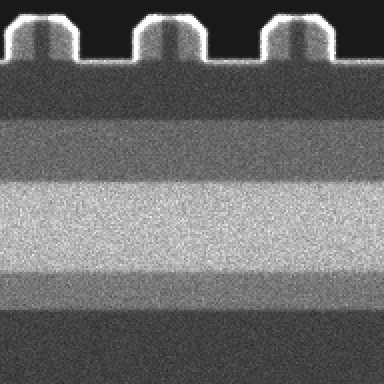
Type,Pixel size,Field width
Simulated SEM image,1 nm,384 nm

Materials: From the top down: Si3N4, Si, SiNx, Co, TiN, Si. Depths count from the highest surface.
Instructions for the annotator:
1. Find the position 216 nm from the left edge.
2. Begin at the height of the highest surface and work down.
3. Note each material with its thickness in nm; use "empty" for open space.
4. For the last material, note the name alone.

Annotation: empty 44, Si 60, SiNx 62, Co 90, TiN 38, Si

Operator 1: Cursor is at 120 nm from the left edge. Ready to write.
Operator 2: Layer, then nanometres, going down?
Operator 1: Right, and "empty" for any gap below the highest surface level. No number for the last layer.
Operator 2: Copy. empty 44, Si 60, SiNx 62, Co 90, TiN 38, Si